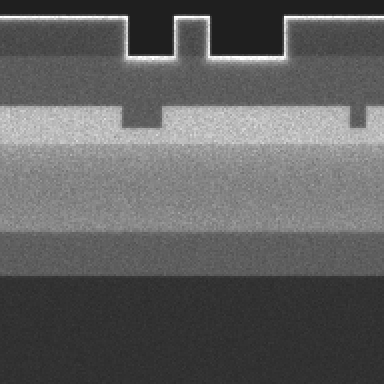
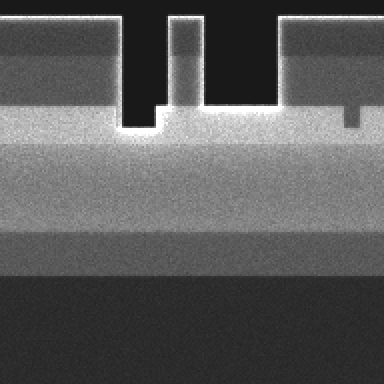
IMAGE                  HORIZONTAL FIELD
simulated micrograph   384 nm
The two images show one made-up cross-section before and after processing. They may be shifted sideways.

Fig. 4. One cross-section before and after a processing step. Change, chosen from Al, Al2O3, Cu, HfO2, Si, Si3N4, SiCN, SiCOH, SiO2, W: SiO2 removed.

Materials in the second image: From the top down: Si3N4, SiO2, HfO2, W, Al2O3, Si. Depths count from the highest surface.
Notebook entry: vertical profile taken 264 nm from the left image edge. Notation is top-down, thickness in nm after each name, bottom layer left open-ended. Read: empty 90, HfO2 38, W 88, Al2O3 44, Si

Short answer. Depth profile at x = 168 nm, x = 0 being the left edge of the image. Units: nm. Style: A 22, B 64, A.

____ Si3N4 40, SiO2 50, HfO2 38, W 88, Al2O3 44, Si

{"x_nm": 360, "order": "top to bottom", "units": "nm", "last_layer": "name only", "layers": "Si3N4 40, SiO2 50, HfO2 38, W 88, Al2O3 44, Si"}